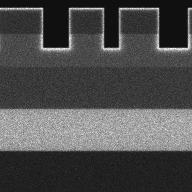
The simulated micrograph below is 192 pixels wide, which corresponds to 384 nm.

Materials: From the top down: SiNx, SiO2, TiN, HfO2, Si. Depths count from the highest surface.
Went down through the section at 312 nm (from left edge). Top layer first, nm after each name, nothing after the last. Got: SiNx 52, SiO2 66, TiN 84, HfO2 84, Si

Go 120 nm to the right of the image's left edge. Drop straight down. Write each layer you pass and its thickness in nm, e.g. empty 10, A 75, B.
empty 80, SiO2 38, TiN 84, HfO2 84, Si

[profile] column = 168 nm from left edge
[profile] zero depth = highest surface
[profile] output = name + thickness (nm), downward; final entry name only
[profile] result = SiNx 52, SiO2 66, TiN 84, HfO2 84, Si